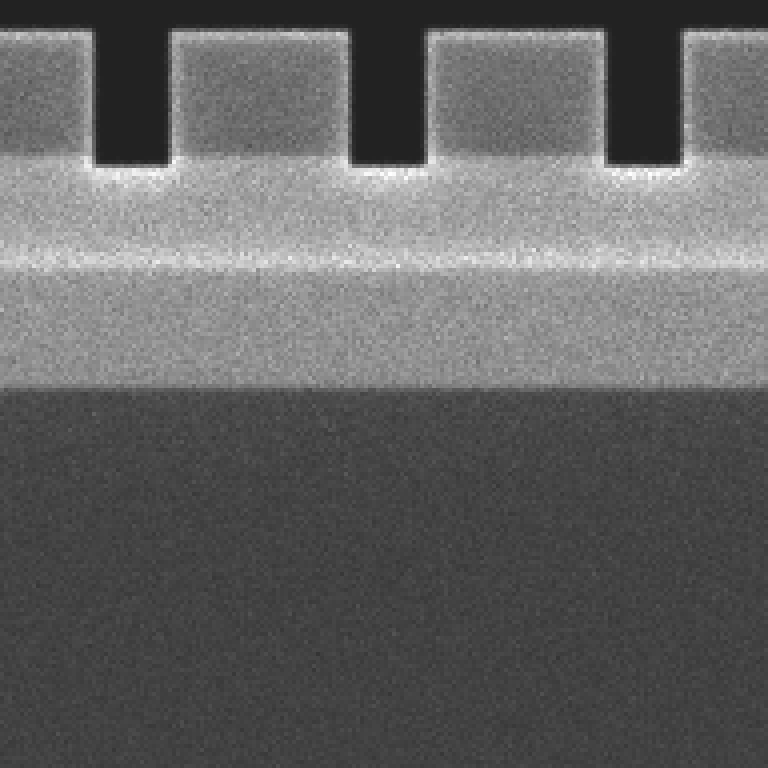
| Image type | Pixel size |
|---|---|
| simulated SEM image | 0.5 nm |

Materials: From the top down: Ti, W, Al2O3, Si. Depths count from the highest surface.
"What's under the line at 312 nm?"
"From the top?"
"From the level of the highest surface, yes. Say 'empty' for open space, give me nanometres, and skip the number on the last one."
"empty 68, W 50, Al2O3 60, Si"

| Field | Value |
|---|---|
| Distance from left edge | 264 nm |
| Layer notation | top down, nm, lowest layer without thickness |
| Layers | Ti 62, W 56, Al2O3 60, Si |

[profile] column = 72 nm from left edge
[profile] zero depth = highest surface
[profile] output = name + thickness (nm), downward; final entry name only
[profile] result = empty 68, W 50, Al2O3 60, Si